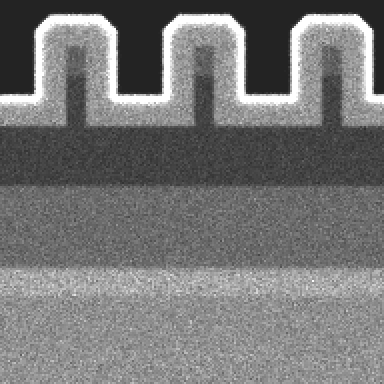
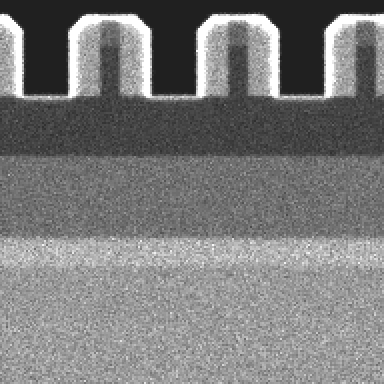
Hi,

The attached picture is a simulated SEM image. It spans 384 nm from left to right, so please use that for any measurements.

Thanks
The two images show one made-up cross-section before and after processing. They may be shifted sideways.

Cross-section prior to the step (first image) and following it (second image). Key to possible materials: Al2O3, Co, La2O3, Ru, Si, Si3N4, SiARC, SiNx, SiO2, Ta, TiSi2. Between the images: Al2O3 was removed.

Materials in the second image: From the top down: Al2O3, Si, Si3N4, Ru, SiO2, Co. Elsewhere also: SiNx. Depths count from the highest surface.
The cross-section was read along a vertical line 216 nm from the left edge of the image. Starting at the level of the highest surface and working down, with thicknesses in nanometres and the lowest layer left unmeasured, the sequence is Al2O3 80, Si 60, Si3N4 82, Ru 28, SiO2 54, Co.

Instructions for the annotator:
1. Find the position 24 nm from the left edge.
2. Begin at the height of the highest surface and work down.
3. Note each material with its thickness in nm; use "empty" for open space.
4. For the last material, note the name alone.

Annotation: empty 80, Si 60, Si3N4 82, Ru 28, SiO2 54, Co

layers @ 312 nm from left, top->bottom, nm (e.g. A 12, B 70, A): empty 80, Si 60, Si3N4 82, Ru 28, SiO2 54, Co